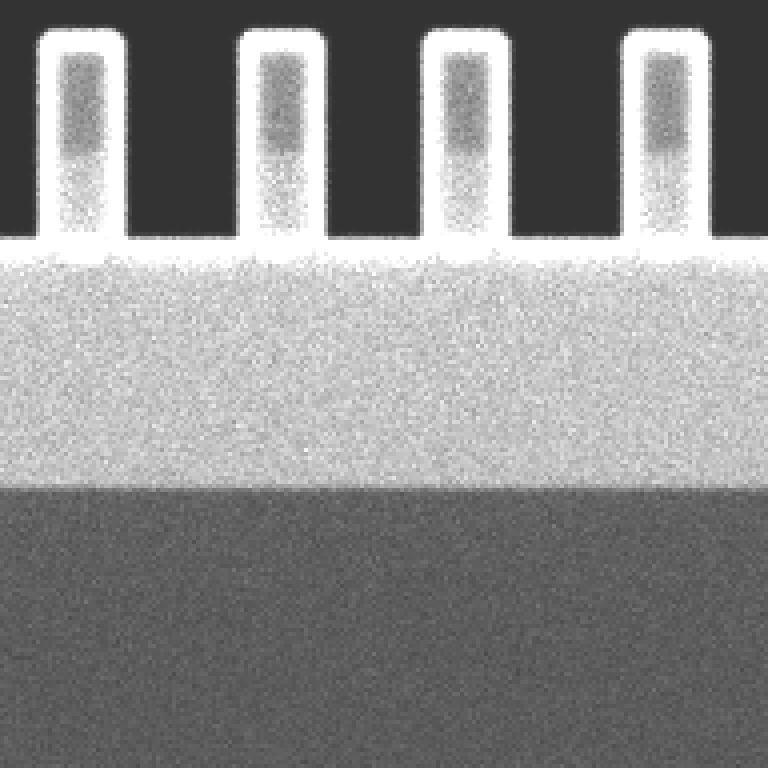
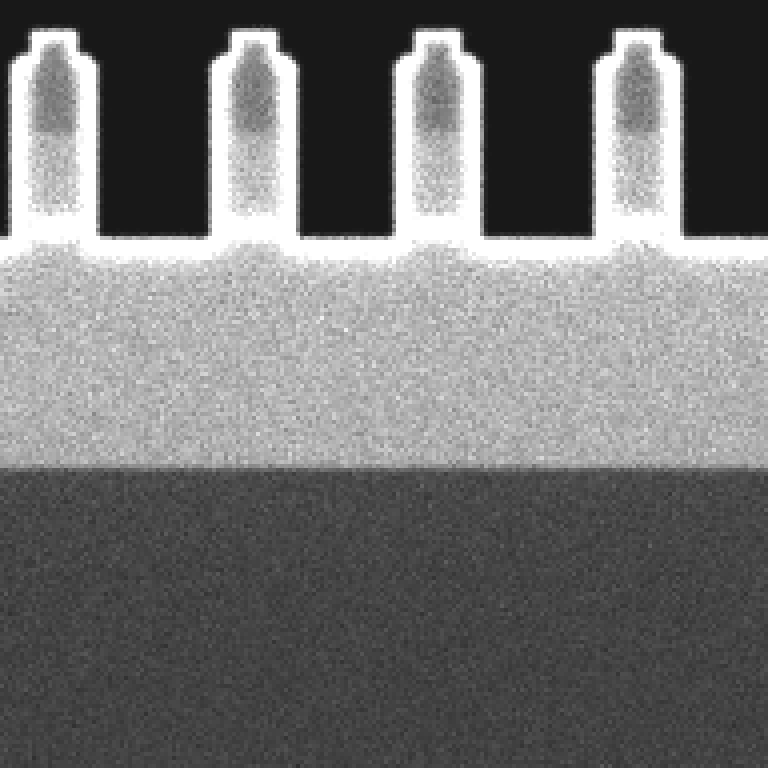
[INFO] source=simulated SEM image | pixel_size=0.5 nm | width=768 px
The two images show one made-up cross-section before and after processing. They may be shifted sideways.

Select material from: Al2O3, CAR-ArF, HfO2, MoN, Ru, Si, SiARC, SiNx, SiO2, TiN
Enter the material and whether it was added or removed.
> SiO2 / removed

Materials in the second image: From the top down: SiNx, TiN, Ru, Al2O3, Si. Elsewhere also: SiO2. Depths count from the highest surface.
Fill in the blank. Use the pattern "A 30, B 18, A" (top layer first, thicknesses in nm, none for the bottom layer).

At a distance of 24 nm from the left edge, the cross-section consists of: SiNx 50, TiN 42, Ru 12, Al2O3 114, Si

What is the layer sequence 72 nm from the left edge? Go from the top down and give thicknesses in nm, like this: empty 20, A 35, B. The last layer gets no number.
empty 104, Al2O3 114, Si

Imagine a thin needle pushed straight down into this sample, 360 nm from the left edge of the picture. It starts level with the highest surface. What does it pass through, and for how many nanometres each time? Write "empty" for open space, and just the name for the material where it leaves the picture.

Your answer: empty 104, Al2O3 114, Si